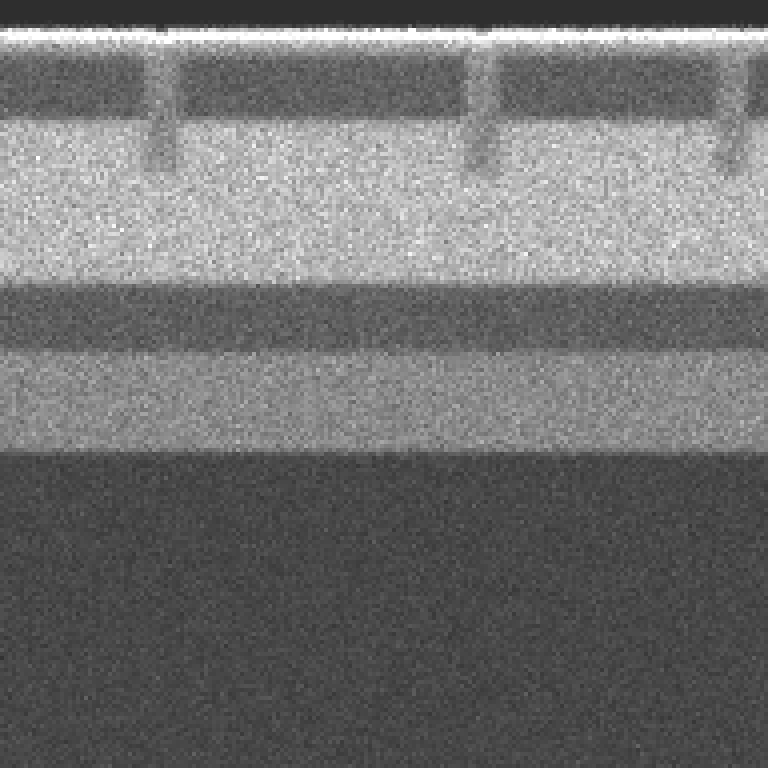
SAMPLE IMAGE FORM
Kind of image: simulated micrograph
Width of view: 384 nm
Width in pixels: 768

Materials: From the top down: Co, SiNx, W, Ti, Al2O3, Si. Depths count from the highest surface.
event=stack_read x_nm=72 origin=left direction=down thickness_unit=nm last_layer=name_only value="Co 72, W 54, Ti 34, Al2O3 50, Si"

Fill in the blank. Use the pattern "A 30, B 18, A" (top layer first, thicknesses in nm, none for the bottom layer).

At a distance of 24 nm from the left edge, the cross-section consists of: Co 12, SiNx 32, W 82, Ti 34, Al2O3 50, Si